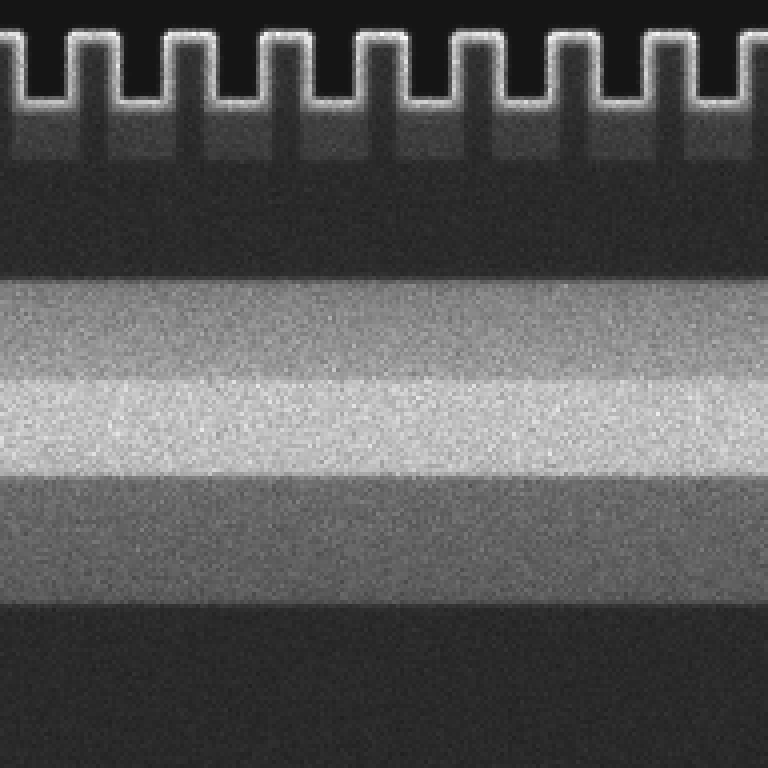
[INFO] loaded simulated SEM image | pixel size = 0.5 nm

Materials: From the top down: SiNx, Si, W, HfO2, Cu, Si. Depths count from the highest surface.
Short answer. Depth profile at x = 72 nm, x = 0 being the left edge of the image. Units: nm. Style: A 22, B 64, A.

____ empty 34, SiNx 30, Si 60, W 50, HfO2 48, Cu 64, Si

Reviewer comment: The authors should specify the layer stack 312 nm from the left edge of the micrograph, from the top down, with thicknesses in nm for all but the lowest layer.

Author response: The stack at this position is empty 34, SiNx 30, Si 60, W 50, HfO2 48, Cu 64, Si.